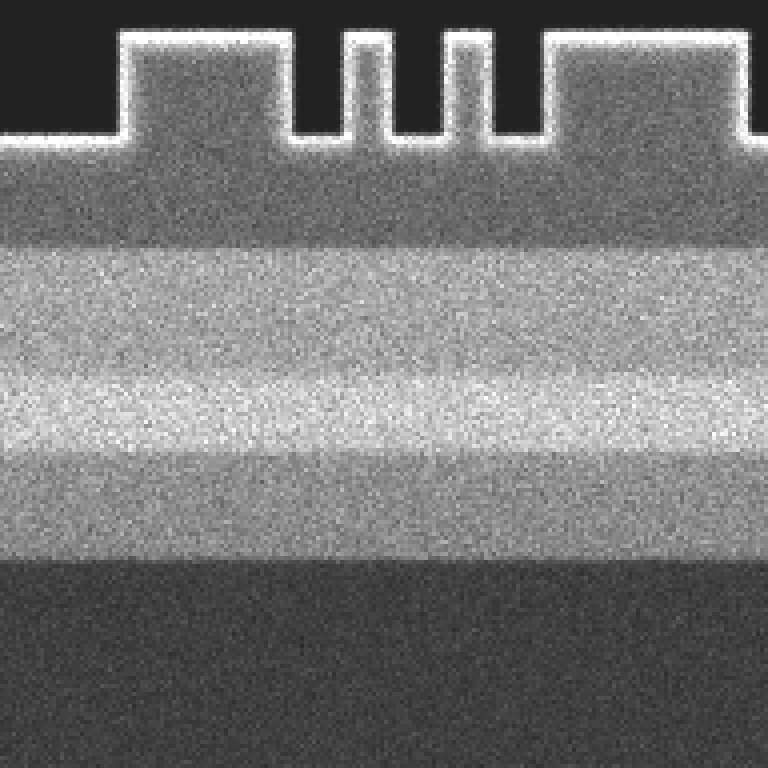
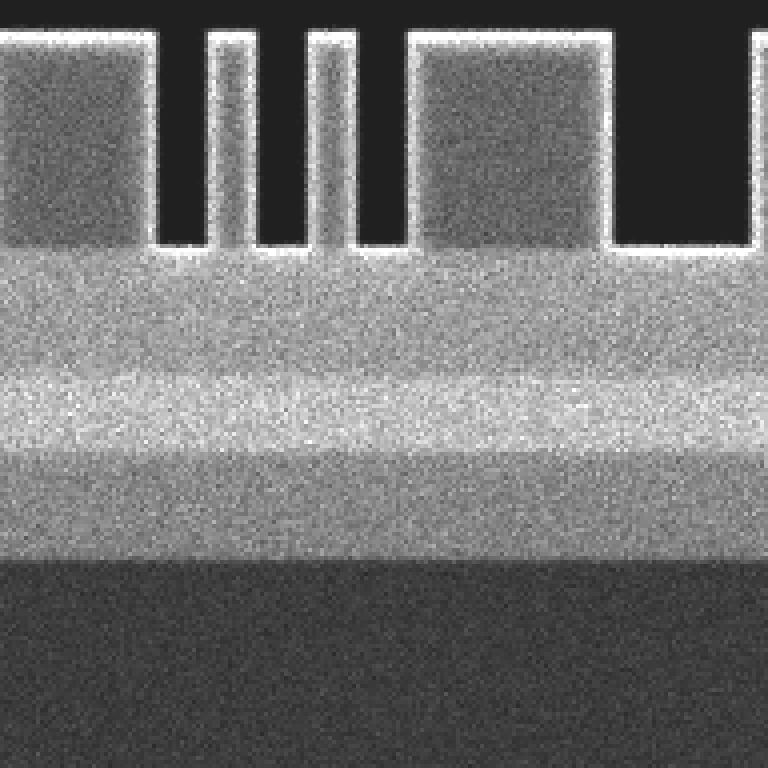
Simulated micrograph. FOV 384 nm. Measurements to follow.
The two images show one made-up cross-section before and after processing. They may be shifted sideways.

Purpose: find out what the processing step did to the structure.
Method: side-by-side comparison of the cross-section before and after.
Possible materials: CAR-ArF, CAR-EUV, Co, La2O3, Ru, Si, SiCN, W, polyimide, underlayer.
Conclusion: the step removed underlayer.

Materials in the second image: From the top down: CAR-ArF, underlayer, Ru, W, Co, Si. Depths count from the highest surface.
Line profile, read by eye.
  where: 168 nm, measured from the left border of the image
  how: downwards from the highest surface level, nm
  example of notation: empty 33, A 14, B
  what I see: CAR-ArF 52, underlayer 56, Ru 64, W 38, Co 54, Si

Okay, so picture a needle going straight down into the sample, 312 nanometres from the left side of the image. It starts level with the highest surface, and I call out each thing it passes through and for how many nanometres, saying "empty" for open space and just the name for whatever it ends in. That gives empty 108, Ru 64, W 38, Co 54, Si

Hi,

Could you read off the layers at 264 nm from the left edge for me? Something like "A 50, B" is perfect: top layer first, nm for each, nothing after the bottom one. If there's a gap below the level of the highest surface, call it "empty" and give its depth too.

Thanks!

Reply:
CAR-ArF 52, underlayer 56, Ru 64, W 38, Co 54, Si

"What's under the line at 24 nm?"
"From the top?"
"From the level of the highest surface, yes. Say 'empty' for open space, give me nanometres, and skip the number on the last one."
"CAR-ArF 52, underlayer 56, Ru 64, W 38, Co 54, Si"